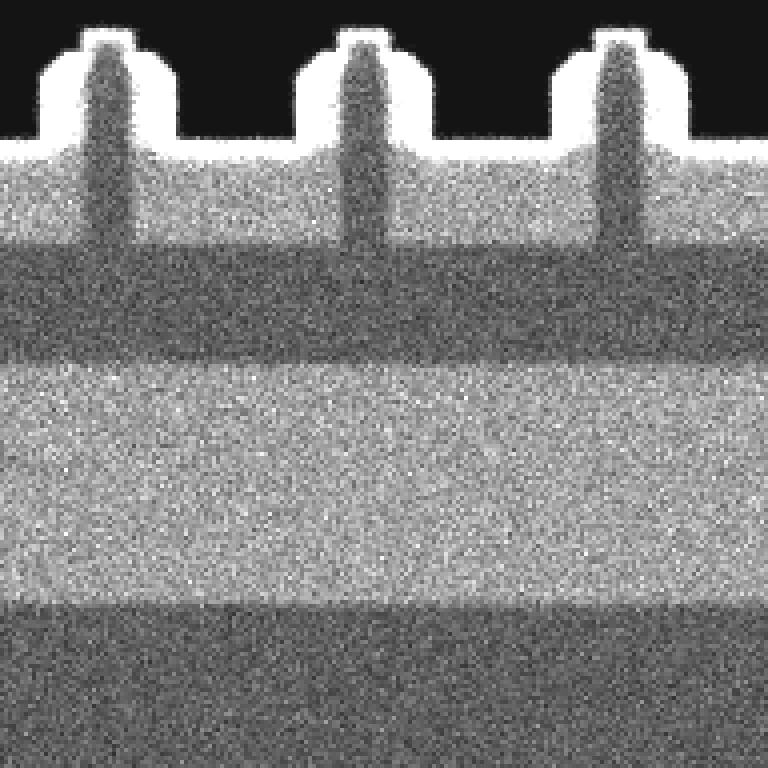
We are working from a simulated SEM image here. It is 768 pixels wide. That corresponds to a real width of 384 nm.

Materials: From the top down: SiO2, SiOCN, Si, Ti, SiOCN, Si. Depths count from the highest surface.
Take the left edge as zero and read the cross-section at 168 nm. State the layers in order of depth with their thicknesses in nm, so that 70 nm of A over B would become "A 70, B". empty 12, SiO2 44, SiOCN 50, Si 60, Ti 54, SiOCN 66, Si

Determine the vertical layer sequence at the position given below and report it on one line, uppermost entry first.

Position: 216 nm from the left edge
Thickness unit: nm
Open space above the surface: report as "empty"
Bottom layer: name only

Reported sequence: empty 56, SiOCN 50, Si 60, Ti 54, SiOCN 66, Si